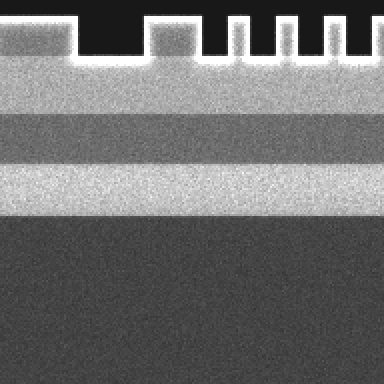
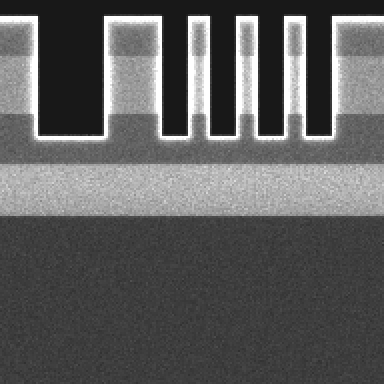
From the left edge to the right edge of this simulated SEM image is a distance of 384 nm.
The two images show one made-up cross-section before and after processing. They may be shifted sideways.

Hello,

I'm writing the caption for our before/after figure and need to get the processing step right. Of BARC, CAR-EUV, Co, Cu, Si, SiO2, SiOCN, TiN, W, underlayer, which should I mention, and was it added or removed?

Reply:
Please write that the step removed SiO2 and SiOCN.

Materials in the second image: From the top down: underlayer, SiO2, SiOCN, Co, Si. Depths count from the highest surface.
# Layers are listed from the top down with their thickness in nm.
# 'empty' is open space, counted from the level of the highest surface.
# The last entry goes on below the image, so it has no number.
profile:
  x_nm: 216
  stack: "empty 120, SiOCN 28, Co 52, Si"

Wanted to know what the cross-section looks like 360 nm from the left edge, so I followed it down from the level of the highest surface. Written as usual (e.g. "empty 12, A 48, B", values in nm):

underlayer 40, SiO2 58, SiOCN 50, Co 52, Si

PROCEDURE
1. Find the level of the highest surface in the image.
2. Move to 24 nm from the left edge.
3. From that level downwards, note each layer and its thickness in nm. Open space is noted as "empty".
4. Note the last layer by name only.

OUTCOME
underlayer 40, SiO2 58, SiOCN 50, Co 52, Si